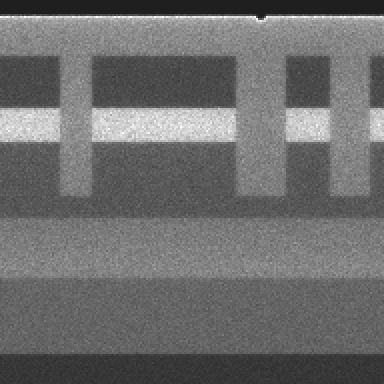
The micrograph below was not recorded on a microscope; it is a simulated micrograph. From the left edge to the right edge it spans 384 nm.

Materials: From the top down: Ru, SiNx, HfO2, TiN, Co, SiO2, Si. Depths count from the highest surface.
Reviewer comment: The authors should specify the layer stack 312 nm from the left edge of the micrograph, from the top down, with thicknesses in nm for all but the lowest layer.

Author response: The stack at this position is Ru 40, SiNx 52, HfO2 34, TiN 76, Co 60, SiO2 76, Si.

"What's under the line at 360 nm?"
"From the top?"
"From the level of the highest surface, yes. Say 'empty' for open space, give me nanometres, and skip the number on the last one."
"Ru 180, TiN 22, Co 60, SiO2 76, Si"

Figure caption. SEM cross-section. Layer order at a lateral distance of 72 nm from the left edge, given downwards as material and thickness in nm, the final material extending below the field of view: Ru 180, TiN 22, Co 60, SiO2 76, Si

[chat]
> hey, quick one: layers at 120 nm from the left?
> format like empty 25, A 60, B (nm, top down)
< Ru 40, SiNx 52, HfO2 34, TiN 76, Co 60, SiO2 76, Si